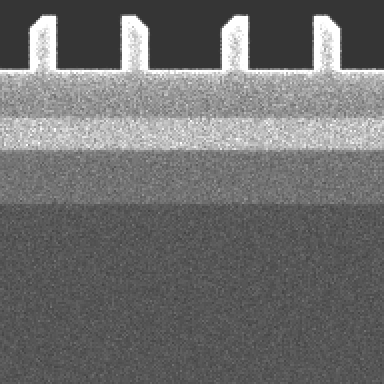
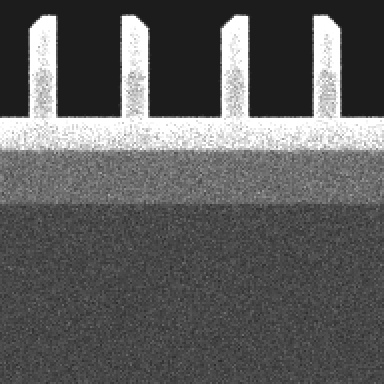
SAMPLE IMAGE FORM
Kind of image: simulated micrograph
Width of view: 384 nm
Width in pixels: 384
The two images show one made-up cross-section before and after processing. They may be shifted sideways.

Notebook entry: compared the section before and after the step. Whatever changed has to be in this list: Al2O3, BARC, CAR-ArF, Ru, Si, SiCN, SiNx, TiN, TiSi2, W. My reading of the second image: TiN removed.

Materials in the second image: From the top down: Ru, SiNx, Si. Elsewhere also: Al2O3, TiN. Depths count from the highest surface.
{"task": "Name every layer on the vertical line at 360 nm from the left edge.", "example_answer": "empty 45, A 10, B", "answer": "empty 102, Ru 32, SiNx 54, Si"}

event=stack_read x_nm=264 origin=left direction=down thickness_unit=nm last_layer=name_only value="empty 102, Ru 32, SiNx 54, Si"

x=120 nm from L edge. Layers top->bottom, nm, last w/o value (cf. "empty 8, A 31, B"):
empty 102, Ru 32, SiNx 54, Si